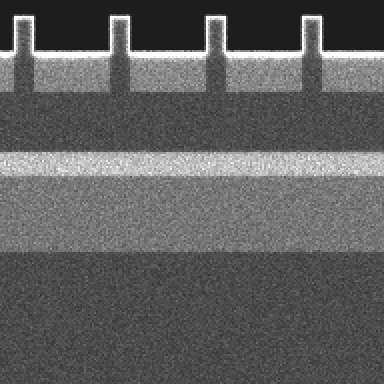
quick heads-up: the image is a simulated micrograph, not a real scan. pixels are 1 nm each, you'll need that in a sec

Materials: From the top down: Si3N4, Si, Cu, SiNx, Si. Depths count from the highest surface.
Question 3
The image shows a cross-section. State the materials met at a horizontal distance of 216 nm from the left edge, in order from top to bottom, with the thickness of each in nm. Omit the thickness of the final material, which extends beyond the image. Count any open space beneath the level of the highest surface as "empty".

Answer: Si 136, Cu 24, SiNx 76, Si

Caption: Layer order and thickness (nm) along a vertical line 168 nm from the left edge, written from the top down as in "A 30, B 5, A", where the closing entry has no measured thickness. empty 36, Si3N4 40, Si 60, Cu 24, SiNx 76, Si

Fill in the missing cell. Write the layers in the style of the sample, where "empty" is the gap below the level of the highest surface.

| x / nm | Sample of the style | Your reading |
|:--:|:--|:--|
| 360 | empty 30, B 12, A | empty 36, Si3N4 40, Si 60, Cu 24, SiNx 76, Si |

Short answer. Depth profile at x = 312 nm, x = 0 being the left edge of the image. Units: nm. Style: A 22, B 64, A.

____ Si 136, Cu 24, SiNx 76, Si